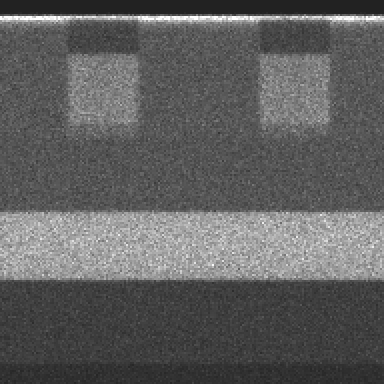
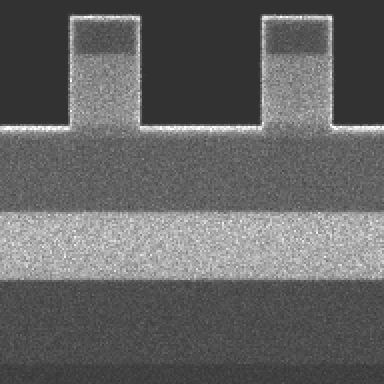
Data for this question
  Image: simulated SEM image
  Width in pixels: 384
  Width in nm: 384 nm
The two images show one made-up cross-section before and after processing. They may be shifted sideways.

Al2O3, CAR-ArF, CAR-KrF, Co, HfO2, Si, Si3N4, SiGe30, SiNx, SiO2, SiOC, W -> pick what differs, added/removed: Al2O3 removed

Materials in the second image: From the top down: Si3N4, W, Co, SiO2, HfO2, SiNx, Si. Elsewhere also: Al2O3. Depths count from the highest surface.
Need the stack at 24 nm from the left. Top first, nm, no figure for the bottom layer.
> empty 110, Al2O3 12, SiO2 74, HfO2 68, SiNx 84, Si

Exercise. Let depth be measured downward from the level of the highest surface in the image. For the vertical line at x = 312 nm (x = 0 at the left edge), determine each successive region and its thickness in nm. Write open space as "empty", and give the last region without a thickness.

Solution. Si3N4 38, W 70, Co 14, SiO2 74, HfO2 68, SiNx 84, Si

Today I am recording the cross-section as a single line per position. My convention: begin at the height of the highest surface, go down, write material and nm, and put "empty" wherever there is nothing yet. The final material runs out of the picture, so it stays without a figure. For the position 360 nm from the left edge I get empty 110, Al2O3 12, SiO2 74, HfO2 68, SiNx 84, Si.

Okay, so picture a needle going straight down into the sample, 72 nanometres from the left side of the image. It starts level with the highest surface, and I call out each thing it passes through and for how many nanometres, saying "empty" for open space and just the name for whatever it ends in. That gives Si3N4 38, W 70, Co 14, SiO2 74, HfO2 68, SiNx 84, Si